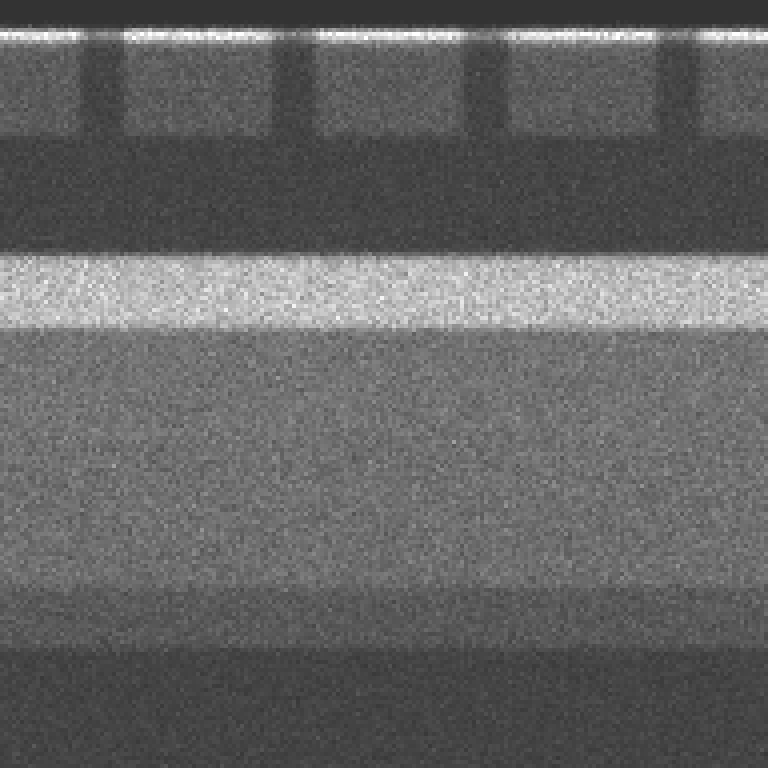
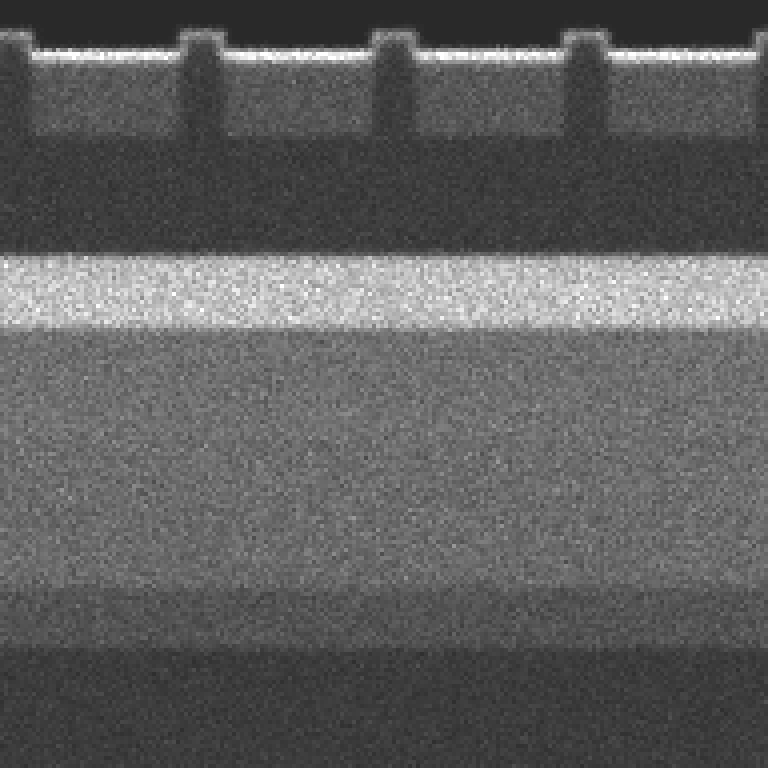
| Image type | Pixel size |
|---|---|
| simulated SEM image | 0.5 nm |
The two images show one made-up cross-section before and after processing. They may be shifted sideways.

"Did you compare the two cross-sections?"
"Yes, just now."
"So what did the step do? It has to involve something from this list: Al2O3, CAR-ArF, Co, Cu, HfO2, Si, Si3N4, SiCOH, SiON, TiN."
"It removed Si3N4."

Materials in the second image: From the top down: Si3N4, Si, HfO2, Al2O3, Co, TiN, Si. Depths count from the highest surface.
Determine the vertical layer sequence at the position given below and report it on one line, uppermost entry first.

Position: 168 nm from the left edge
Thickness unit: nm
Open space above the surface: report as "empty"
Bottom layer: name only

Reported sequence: empty 10, Si3N4 42, Si 60, HfO2 36, Al2O3 54, Co 76, TiN 30, Si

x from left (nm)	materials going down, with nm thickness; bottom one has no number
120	empty 10, Si3N4 42, Si 60, HfO2 36, Al2O3 54, Co 76, TiN 30, Si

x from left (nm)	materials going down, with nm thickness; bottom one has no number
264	empty 10, Si3N4 42, Si 60, HfO2 36, Al2O3 54, Co 76, TiN 30, Si